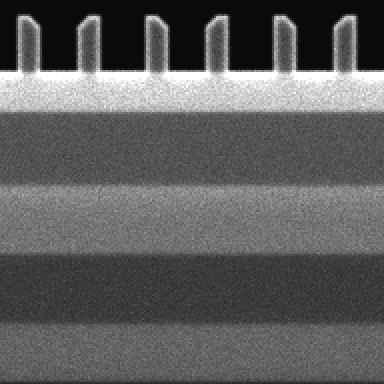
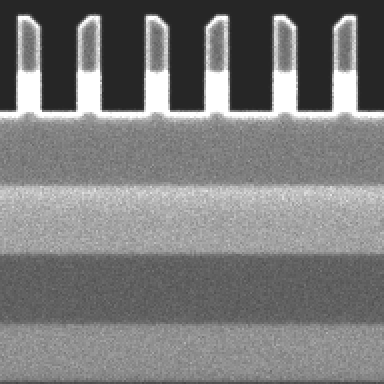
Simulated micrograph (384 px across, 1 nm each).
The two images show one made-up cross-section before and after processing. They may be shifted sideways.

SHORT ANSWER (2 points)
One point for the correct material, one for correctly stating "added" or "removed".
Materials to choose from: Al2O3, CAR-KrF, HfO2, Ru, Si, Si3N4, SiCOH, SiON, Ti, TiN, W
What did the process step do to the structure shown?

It removed HfO2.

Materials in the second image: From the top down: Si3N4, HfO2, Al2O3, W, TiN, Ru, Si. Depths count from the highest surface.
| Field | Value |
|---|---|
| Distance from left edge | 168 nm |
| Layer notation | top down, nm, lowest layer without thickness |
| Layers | empty 96, Al2O3 74, W 68, TiN 70, Ru 58, Si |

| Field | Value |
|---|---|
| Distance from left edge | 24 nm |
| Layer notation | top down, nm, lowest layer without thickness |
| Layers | Si3N4 56, HfO2 40, Al2O3 74, W 68, TiN 70, Ru 58, Si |